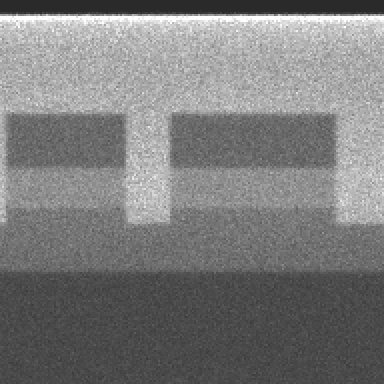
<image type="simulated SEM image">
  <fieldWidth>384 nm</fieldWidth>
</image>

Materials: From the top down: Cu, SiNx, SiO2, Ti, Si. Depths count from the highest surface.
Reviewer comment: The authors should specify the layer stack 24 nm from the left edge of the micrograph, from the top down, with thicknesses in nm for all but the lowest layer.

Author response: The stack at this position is Cu 98, SiNx 54, SiO2 40, Ti 64, Si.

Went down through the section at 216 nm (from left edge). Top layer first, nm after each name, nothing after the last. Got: Cu 98, SiNx 54, SiO2 40, Ti 64, Si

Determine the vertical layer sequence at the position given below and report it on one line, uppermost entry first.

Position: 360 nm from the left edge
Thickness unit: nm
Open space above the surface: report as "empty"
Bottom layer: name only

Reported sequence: Cu 208, Ti 48, Si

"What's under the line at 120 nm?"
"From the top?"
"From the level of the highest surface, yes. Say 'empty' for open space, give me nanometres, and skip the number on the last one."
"Cu 98, SiNx 54, SiO2 40, Ti 64, Si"